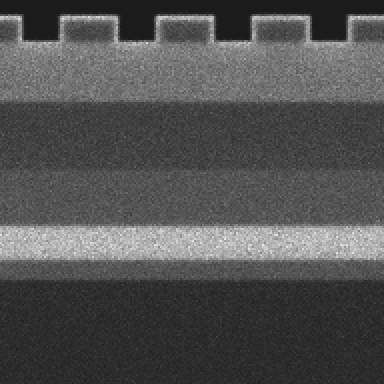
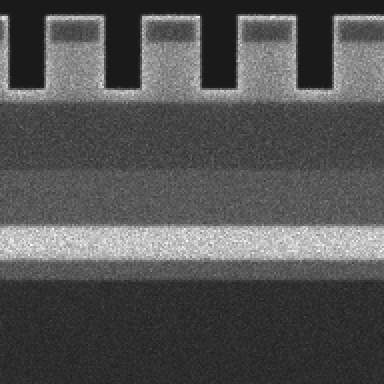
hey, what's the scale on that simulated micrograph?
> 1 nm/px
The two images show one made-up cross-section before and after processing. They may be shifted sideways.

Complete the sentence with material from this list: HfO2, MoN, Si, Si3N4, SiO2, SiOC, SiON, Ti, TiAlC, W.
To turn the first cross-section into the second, W must be removed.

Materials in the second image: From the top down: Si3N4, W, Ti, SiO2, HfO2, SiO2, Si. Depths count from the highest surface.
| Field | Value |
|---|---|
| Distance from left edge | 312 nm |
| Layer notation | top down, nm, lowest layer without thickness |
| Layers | empty 74, W 12, Ti 68, SiO2 56, HfO2 34, SiO2 20, Si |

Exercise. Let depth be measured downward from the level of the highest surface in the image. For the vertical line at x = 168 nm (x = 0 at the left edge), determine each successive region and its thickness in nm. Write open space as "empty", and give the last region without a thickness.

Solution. Si3N4 26, W 60, Ti 68, SiO2 56, HfO2 34, SiO2 20, Si